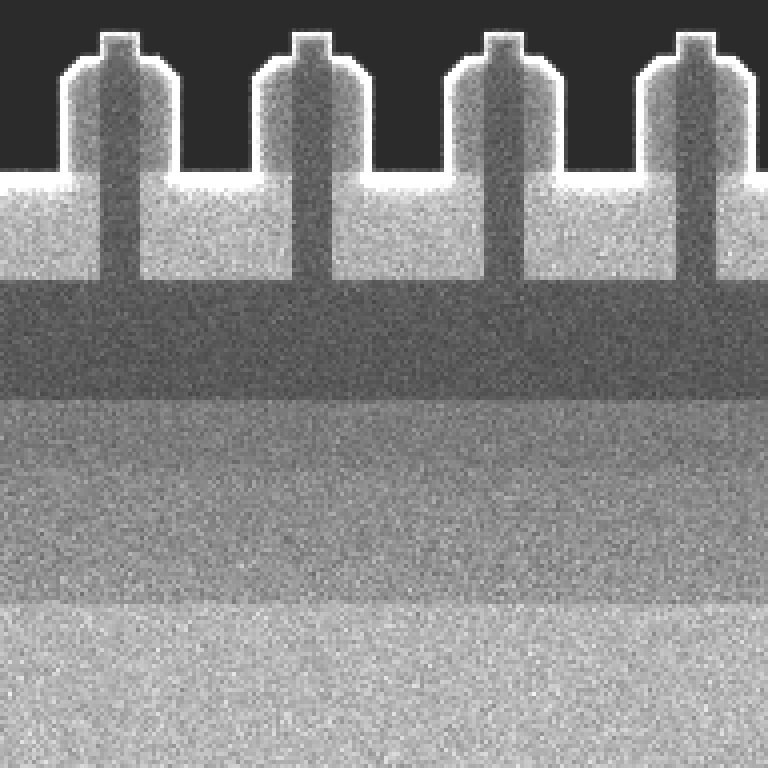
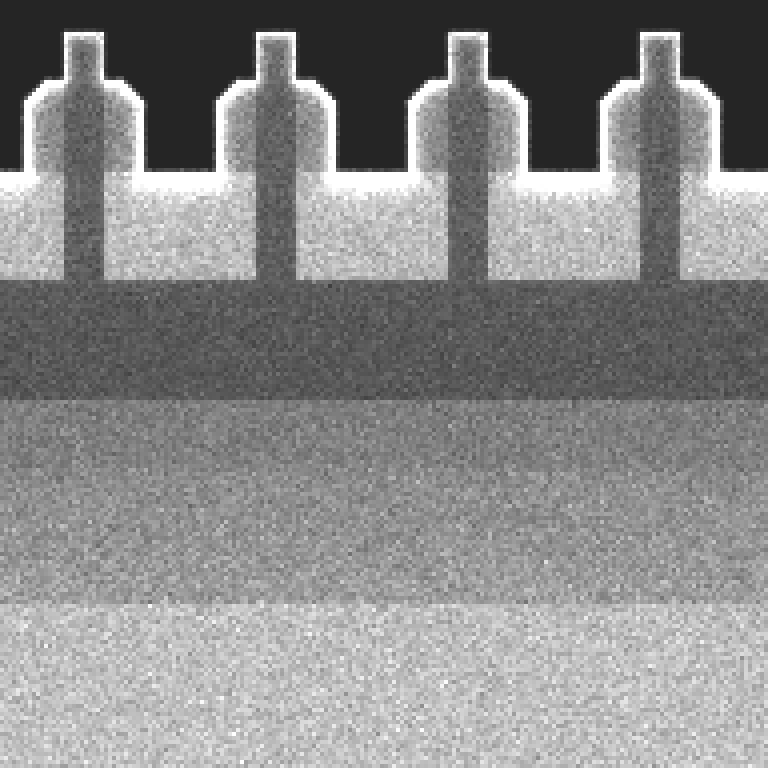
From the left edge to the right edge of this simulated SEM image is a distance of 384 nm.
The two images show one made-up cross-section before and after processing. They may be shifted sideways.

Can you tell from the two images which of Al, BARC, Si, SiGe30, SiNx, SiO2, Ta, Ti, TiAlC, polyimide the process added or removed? Yes, it removed SiNx.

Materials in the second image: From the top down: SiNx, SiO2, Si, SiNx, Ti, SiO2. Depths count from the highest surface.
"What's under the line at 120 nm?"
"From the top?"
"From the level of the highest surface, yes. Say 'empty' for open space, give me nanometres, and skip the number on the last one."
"empty 24, SiNx 46, SiO2 54, Si 60, SiNx 34, Ti 68, SiO2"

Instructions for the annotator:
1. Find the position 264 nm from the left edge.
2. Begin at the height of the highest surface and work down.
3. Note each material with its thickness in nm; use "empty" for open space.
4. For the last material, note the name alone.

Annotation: empty 70, SiO2 54, Si 60, SiNx 34, Ti 68, SiO2